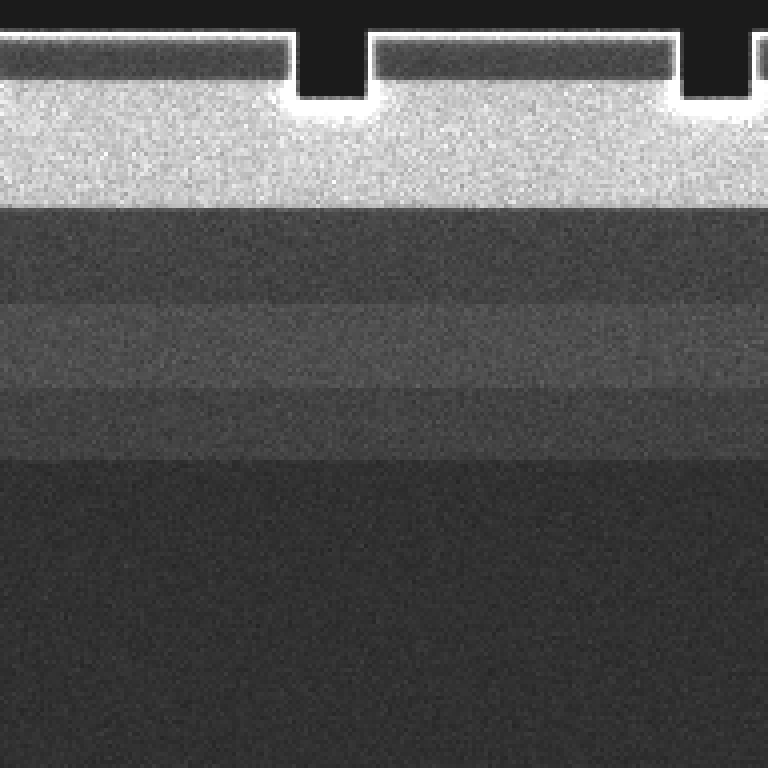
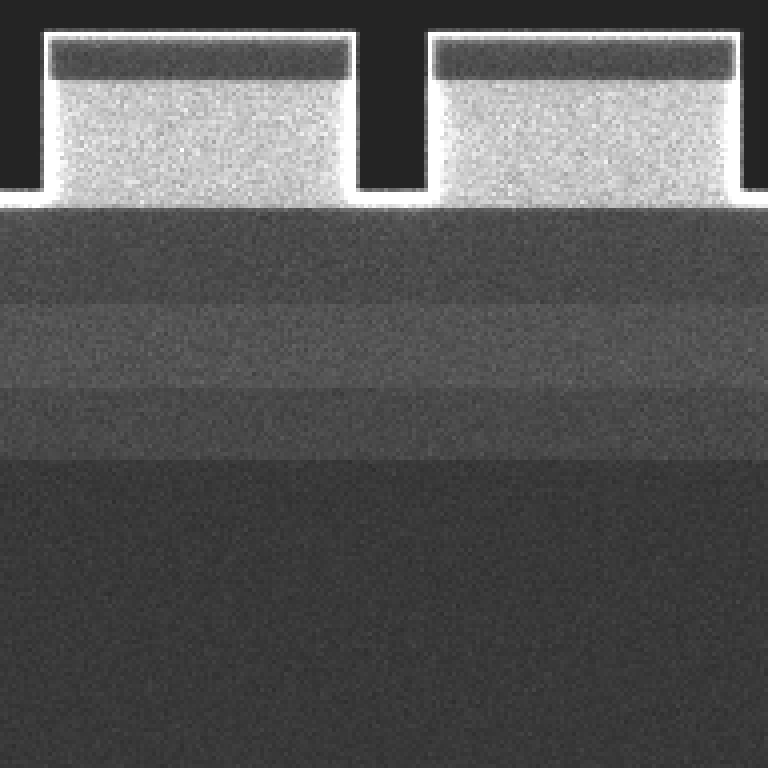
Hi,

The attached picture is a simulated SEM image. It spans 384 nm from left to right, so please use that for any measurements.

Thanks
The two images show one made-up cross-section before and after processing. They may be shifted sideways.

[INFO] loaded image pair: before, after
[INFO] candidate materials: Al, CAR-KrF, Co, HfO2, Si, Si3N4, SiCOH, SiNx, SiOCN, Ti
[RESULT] removed HfO2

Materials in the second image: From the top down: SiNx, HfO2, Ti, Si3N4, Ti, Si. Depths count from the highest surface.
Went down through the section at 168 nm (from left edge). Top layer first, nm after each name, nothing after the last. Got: SiNx 24, HfO2 64, Ti 48, Si3N4 42, Ti 36, Si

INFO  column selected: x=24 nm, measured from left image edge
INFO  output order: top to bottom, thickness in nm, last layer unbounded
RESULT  SiNx 24, HfO2 64, Ti 48, Si3N4 42, Ti 36, Si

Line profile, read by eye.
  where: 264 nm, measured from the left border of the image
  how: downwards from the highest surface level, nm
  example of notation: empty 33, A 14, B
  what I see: SiNx 24, HfO2 64, Ti 48, Si3N4 42, Ti 36, Si